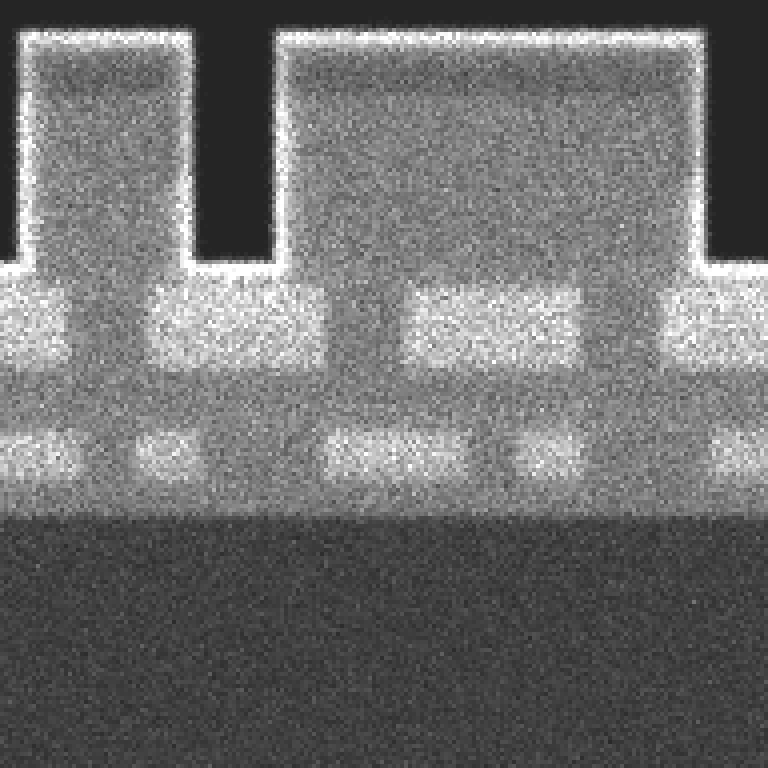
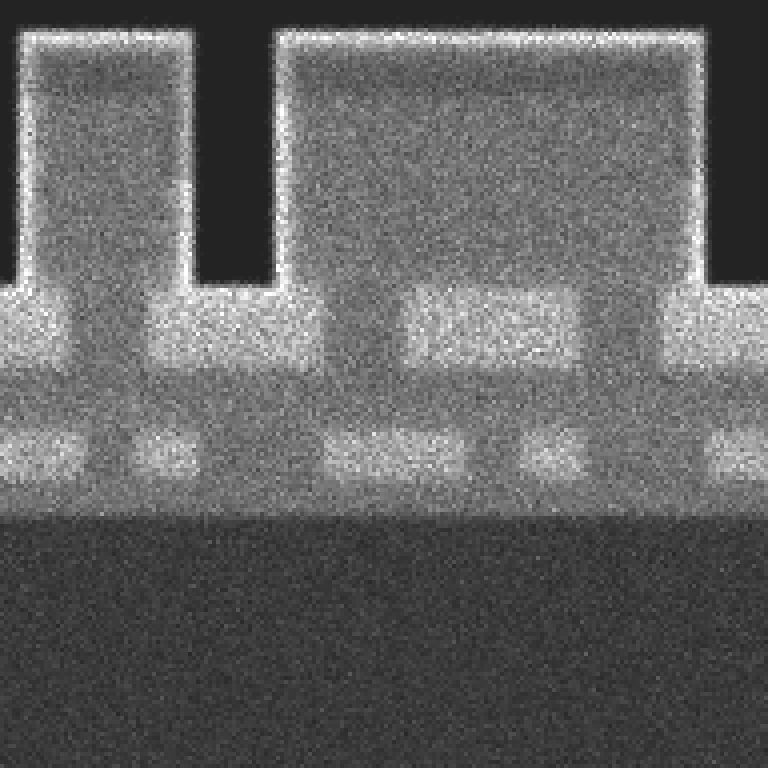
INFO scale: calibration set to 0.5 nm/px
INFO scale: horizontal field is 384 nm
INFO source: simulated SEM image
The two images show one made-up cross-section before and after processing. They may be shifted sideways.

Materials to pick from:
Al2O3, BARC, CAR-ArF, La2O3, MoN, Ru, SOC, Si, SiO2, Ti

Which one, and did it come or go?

Al2O3 - removed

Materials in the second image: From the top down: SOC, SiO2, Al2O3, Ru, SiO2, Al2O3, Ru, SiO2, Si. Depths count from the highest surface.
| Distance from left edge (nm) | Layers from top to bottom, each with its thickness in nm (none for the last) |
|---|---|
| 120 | empty 128, Ru 40, SiO2 18, Al2O3 14, SiO2 42, Si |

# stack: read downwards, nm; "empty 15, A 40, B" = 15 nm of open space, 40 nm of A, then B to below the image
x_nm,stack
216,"SOC 32, SiO2 84, Al2O3 12, Ru 40, SiO2 18, Al2O3 14, Ru 24, SiO2 18, Si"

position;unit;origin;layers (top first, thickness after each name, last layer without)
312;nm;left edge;SOC 32, SiO2 84, Al2O3 12, SiO2 58, Al2O3 14, SiO2 42, Si